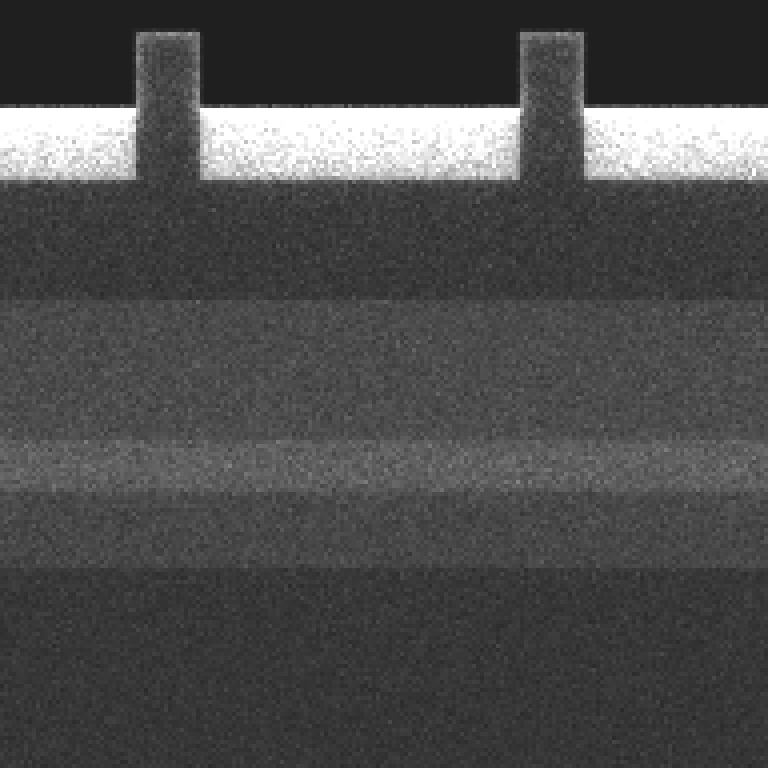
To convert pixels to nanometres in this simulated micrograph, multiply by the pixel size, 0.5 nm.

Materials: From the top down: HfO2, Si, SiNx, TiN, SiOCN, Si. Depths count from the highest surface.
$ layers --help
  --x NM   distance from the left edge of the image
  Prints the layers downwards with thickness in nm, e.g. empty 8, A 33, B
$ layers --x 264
Si 134, SiNx 70, TiN 26, SiOCN 38, Si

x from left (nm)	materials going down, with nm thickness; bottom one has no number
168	empty 38, HfO2 36, Si 60, SiNx 70, TiN 26, SiOCN 38, Si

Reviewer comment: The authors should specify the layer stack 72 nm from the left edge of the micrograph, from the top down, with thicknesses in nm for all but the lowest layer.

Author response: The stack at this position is Si 134, SiNx 70, TiN 26, SiOCN 38, Si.